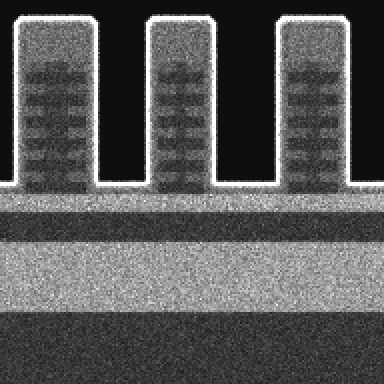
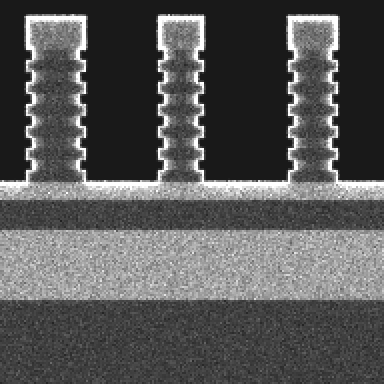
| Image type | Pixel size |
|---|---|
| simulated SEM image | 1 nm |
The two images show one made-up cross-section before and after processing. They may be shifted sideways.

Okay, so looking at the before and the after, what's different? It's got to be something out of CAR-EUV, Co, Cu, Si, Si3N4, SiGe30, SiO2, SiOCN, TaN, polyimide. SiOCN, removed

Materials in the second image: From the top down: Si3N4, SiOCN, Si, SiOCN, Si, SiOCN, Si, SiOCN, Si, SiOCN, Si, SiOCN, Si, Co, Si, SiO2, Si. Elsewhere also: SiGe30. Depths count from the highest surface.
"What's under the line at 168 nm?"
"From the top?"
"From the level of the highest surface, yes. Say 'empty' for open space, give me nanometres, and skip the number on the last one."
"Si3N4 34, SiOCN 10, Si 12, SiOCN 10, Si 12, SiOCN 10, Si 12, SiOCN 10, Si 12, SiOCN 10, Si 12, SiOCN 10, Si 12, Co 18, Si 30, SiO2 70, Si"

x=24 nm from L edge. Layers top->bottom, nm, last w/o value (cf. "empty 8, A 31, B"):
empty 166, Co 18, Si 30, SiO2 70, Si